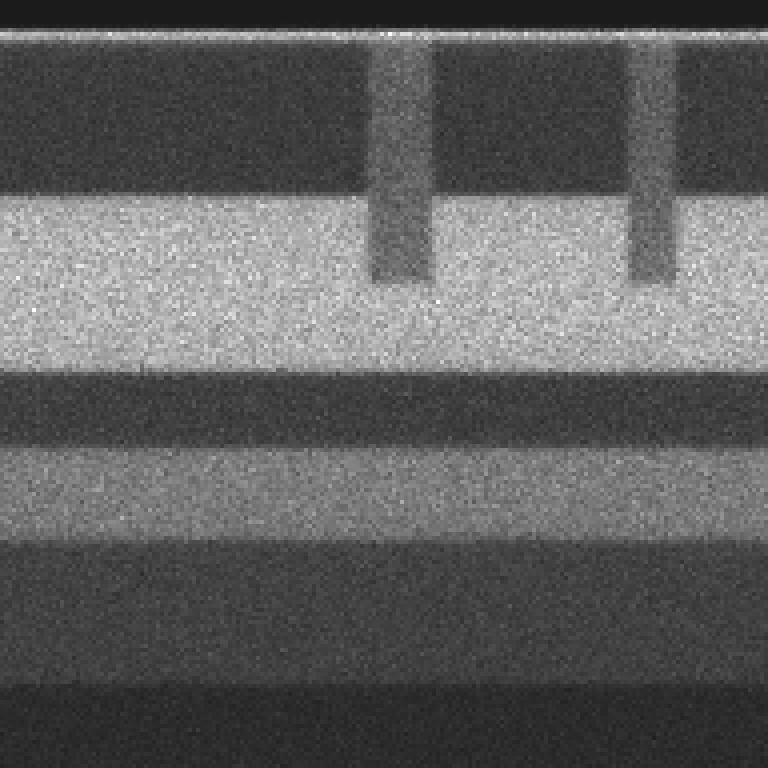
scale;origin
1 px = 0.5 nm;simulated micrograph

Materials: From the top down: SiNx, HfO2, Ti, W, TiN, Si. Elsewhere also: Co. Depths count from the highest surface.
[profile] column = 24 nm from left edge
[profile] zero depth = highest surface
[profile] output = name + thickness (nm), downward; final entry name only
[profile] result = SiNx 82, HfO2 88, Ti 38, W 46, TiN 72, Si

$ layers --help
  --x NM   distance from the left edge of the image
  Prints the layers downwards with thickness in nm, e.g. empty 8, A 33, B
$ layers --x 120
SiNx 82, HfO2 88, Ti 38, W 46, TiN 72, Si